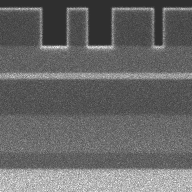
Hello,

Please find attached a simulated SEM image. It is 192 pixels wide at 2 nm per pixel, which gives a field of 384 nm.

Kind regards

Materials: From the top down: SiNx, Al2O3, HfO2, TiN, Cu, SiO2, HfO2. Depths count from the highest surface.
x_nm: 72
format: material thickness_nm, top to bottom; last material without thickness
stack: SiNx 76, Al2O3 54, HfO2 12, TiN 72, Cu 76, SiO2 32, HfO2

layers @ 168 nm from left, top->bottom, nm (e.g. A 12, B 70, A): SiNx 76, Al2O3 54, HfO2 12, TiN 72, Cu 76, SiO2 32, HfO2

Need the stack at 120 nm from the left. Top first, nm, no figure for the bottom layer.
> empty 76, Al2O3 54, HfO2 12, TiN 72, Cu 76, SiO2 32, HfO2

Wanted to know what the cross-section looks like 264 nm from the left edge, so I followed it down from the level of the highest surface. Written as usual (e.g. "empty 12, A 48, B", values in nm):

SiNx 76, Al2O3 54, HfO2 12, TiN 72, Cu 76, SiO2 32, HfO2